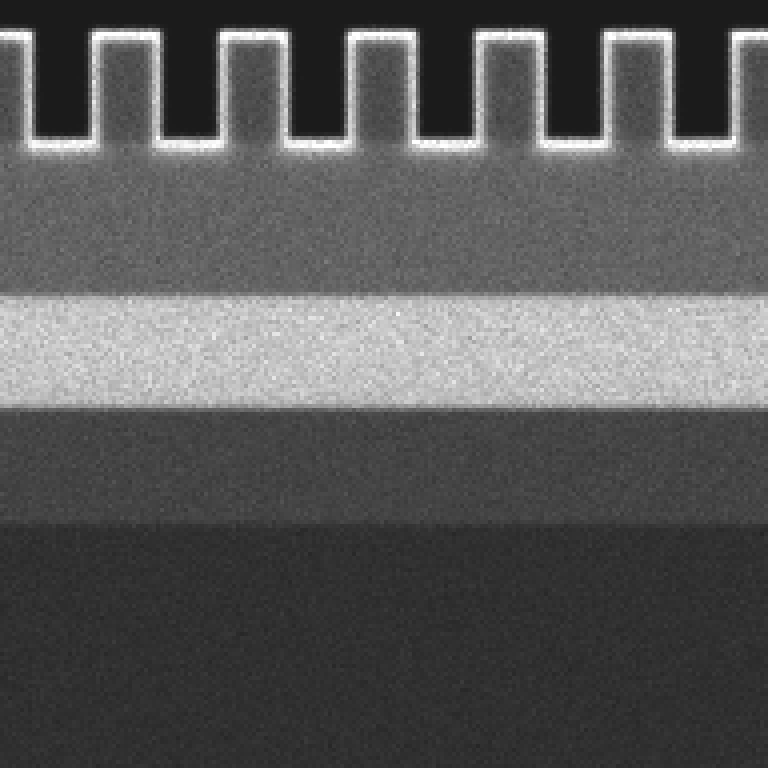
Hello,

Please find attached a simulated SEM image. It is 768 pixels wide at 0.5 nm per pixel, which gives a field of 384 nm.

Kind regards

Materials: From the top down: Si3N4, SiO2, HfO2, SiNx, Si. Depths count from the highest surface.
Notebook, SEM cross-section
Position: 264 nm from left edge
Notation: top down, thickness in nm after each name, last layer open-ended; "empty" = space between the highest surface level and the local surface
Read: Si3N4 54, SiO2 78, HfO2 56, SiNx 58, Si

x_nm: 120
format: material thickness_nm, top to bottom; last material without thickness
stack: Si3N4 54, SiO2 78, HfO2 56, SiNx 58, Si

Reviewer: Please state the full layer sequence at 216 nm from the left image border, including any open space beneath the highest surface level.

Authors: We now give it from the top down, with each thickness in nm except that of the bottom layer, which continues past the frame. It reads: empty 54, SiO2 78, HfO2 56, SiNx 58, Si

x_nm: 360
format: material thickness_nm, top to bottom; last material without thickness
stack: empty 54, SiO2 78, HfO2 56, SiNx 58, Si